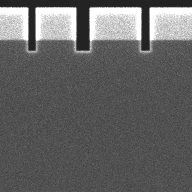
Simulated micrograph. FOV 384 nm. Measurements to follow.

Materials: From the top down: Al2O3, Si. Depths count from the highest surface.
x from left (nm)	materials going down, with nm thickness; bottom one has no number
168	empty 86, Si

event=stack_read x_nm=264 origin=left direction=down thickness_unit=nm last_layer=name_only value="Al2O3 64, Si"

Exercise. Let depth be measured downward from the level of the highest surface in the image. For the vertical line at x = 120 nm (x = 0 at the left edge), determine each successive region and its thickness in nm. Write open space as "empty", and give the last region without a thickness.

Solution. Al2O3 64, Si